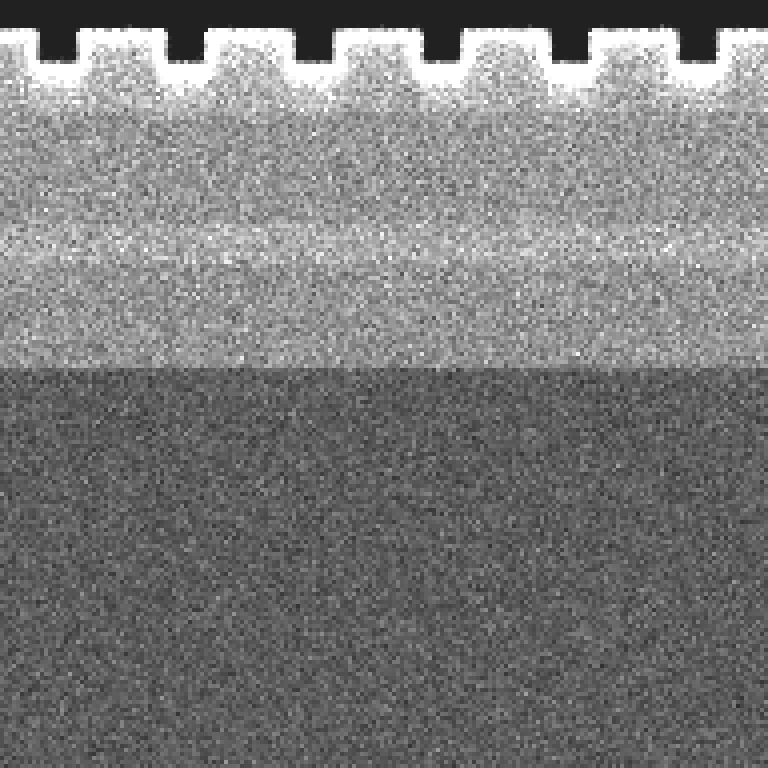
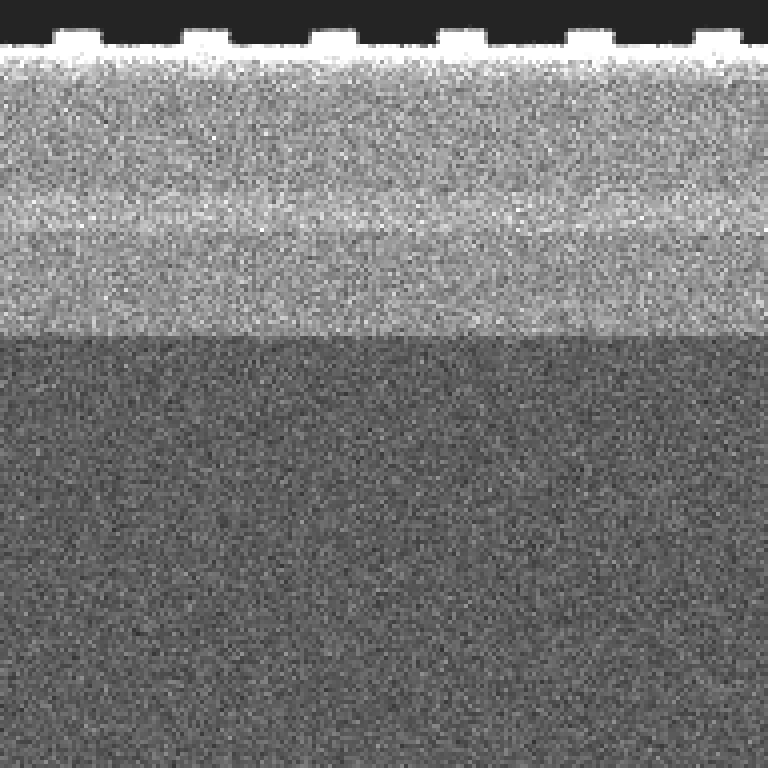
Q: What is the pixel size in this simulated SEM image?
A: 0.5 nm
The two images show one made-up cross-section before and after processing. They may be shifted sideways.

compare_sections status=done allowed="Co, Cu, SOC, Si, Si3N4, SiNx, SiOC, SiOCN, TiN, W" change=removed material="TiN"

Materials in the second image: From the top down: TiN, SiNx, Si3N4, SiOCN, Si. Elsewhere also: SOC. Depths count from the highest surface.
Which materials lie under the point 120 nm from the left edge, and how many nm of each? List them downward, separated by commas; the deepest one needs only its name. empty 8, TiN 16, SiNx 56, Si3N4 20, SiOCN 52, Si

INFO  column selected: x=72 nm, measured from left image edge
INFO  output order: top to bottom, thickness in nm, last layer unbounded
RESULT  empty 8, TiN 16, SiNx 56, Si3N4 20, SiOCN 52, Si